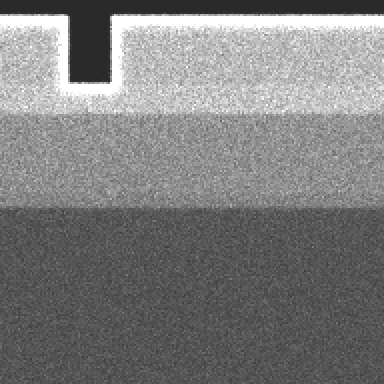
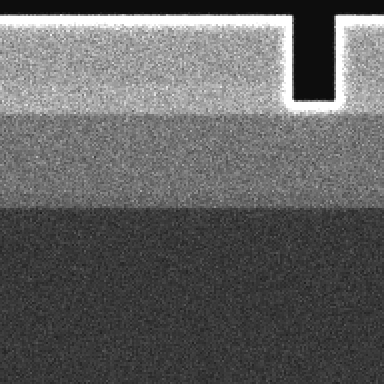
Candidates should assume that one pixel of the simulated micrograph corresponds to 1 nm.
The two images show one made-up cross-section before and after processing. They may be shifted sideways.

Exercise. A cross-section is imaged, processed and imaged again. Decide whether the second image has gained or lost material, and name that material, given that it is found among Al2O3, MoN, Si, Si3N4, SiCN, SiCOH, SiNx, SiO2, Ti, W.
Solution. removed: Al2O3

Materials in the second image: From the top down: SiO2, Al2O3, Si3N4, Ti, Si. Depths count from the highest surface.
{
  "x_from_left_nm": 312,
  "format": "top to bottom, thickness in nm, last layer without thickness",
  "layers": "empty 86, Al2O3 12, Si3N4 80, Ti 14, Si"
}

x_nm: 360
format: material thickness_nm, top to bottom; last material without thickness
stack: SiO2 68, Al2O3 30, Si3N4 80, Ti 14, Si